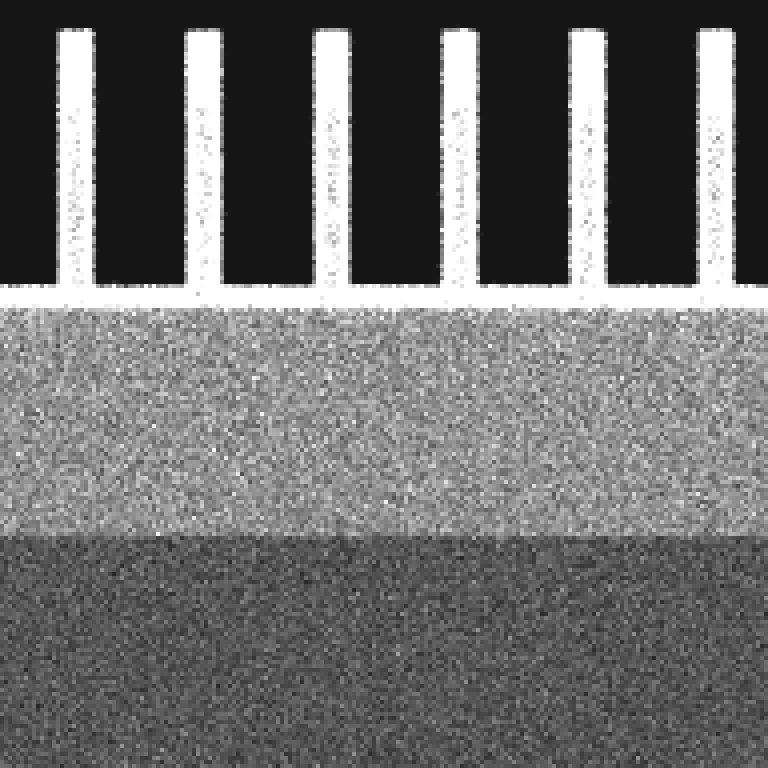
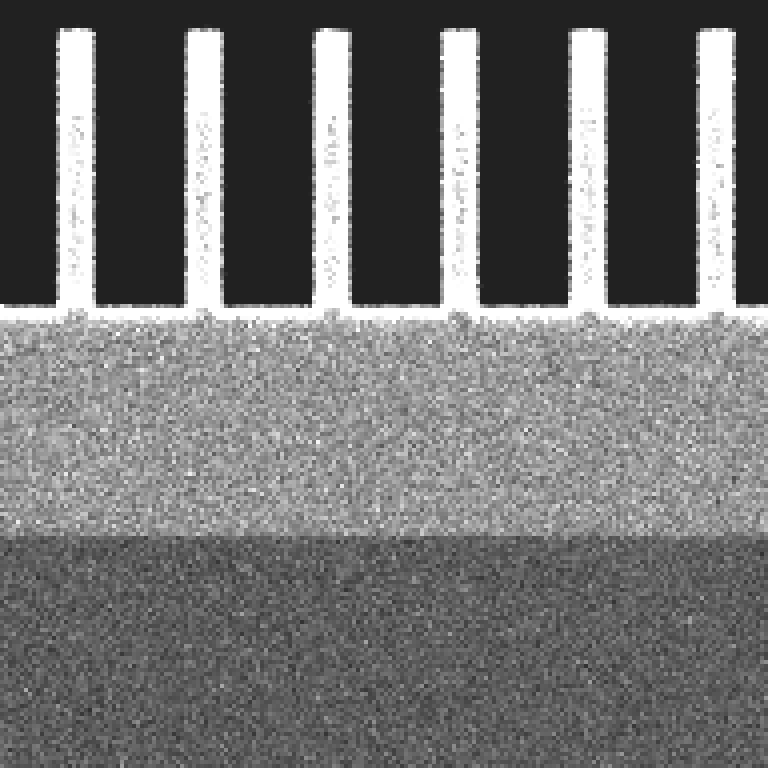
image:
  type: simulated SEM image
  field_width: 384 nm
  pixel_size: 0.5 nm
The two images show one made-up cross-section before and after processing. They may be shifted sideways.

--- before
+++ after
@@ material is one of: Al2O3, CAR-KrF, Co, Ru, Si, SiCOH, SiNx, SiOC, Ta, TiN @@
Co removed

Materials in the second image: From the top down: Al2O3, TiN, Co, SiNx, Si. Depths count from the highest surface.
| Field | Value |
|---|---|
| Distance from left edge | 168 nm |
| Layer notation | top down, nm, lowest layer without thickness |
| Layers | Al2O3 36, TiN 92, Co 10, SiNx 114, Si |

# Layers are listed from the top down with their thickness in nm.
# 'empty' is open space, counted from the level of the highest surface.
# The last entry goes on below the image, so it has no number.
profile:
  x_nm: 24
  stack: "empty 138, SiNx 114, Si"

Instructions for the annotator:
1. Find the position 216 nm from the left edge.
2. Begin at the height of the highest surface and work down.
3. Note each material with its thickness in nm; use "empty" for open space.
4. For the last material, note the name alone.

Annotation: empty 138, SiNx 114, Si